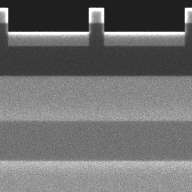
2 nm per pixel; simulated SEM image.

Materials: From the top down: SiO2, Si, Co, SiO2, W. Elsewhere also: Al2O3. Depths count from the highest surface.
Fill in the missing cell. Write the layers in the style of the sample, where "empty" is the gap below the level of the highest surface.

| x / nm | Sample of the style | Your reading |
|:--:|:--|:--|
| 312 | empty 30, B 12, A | empty 48, SiO2 28, Si 60, Co 90, SiO2 80, W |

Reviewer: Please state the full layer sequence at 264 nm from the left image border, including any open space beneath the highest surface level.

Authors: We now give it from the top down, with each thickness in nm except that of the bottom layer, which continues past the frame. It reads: empty 48, SiO2 28, Si 60, Co 90, SiO2 80, W